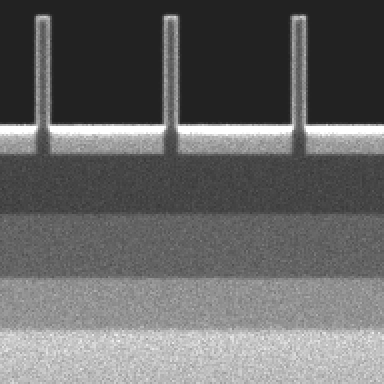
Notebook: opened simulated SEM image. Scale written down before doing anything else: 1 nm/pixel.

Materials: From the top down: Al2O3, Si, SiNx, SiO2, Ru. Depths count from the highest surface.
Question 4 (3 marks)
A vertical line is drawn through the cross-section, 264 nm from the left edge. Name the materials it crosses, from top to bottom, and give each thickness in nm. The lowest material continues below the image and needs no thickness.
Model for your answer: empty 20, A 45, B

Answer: empty 110, Al2O3 28, Si 60, SiNx 64, SiO2 52, Ru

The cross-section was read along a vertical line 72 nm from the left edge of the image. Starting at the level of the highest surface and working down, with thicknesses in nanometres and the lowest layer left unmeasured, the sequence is empty 110, Al2O3 28, Si 60, SiNx 64, SiO2 52, Ru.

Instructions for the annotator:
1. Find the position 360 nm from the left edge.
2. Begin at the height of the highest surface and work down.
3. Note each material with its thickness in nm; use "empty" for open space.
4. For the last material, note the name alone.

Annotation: empty 110, Al2O3 28, Si 60, SiNx 64, SiO2 52, Ru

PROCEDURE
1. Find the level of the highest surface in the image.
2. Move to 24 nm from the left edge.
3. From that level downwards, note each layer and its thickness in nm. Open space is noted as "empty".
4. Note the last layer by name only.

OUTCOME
empty 110, Al2O3 28, Si 60, SiNx 64, SiO2 52, Ru